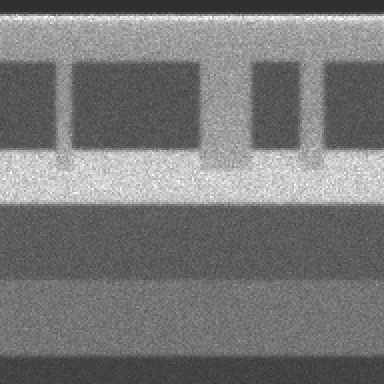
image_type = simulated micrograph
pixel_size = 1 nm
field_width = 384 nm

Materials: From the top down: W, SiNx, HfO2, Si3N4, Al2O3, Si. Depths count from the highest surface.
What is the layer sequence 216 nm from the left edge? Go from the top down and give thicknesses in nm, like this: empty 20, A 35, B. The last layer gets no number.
W 154, HfO2 34, Si3N4 76, Al2O3 76, Si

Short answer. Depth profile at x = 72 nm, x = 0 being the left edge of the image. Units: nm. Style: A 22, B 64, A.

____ W 46, SiNx 88, HfO2 54, Si3N4 76, Al2O3 76, Si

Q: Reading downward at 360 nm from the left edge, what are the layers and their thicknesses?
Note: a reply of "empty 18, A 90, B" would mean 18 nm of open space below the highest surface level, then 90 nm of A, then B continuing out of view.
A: W 46, SiNx 88, HfO2 54, Si3N4 76, Al2O3 76, Si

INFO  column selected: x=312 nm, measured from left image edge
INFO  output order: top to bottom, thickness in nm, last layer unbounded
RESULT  W 154, HfO2 34, Si3N4 76, Al2O3 76, Si